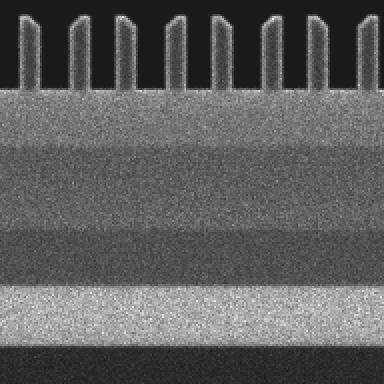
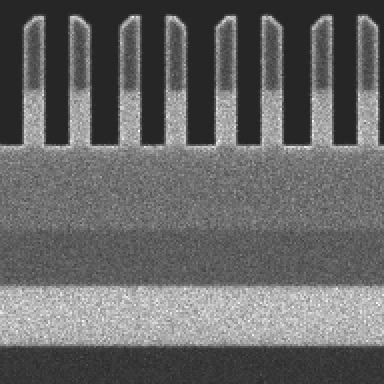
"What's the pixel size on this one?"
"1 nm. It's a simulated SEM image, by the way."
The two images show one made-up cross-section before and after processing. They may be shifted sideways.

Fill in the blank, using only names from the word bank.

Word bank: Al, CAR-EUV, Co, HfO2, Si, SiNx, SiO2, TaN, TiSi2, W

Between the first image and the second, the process removed W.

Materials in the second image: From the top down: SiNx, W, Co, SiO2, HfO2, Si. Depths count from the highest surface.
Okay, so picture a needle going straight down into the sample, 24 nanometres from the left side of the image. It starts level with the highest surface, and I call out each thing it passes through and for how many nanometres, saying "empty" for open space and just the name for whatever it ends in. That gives empty 10, SiNx 64, W 56, Co 84, SiO2 56, HfO2 60, Si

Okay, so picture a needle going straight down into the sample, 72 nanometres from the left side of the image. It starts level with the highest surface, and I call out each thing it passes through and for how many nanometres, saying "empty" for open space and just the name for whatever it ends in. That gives SiNx 74, W 56, Co 84, SiO2 56, HfO2 60, Si